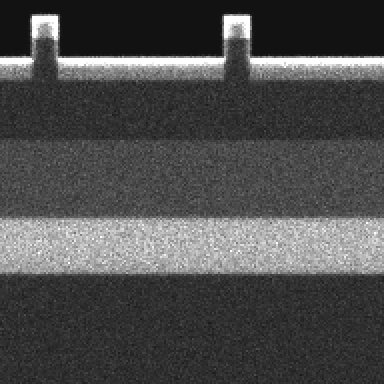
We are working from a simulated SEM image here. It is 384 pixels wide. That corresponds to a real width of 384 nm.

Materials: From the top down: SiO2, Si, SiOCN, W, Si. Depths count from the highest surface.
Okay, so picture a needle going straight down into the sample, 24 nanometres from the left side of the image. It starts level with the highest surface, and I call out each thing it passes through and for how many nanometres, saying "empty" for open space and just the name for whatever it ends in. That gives empty 42, SiO2 22, Si 60, SiOCN 78, W 56, Si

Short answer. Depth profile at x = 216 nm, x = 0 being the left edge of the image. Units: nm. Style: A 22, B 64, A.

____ empty 42, SiO2 22, Si 60, SiOCN 78, W 56, Si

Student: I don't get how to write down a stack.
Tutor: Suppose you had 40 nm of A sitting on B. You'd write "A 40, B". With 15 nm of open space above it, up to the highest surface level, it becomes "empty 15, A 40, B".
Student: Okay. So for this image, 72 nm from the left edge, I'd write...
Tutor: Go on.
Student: empty 42, SiO2 22, Si 60, SiOCN 78, W 56, Si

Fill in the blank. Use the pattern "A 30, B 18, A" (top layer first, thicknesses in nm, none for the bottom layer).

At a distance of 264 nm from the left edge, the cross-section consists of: empty 42, SiO2 22, Si 60, SiOCN 78, W 56, Si